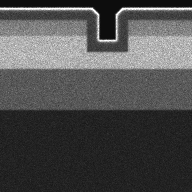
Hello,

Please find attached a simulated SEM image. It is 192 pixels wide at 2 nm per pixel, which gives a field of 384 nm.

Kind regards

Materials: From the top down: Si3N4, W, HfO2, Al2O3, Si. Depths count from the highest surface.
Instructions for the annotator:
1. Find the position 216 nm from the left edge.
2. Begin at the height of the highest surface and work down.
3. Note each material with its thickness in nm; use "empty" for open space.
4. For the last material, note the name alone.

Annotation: empty 64, Si3N4 24, HfO2 34, Al2O3 82, Si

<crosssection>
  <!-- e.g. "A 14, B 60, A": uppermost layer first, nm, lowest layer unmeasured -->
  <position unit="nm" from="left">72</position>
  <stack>Si3N4 24, W 32, HfO2 66, Al2O3 82, Si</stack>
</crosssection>